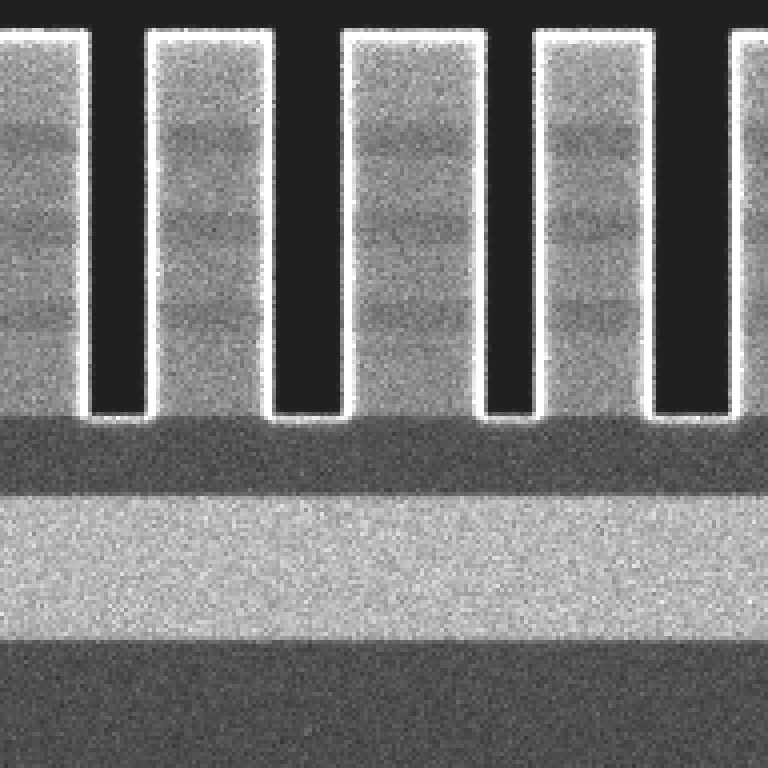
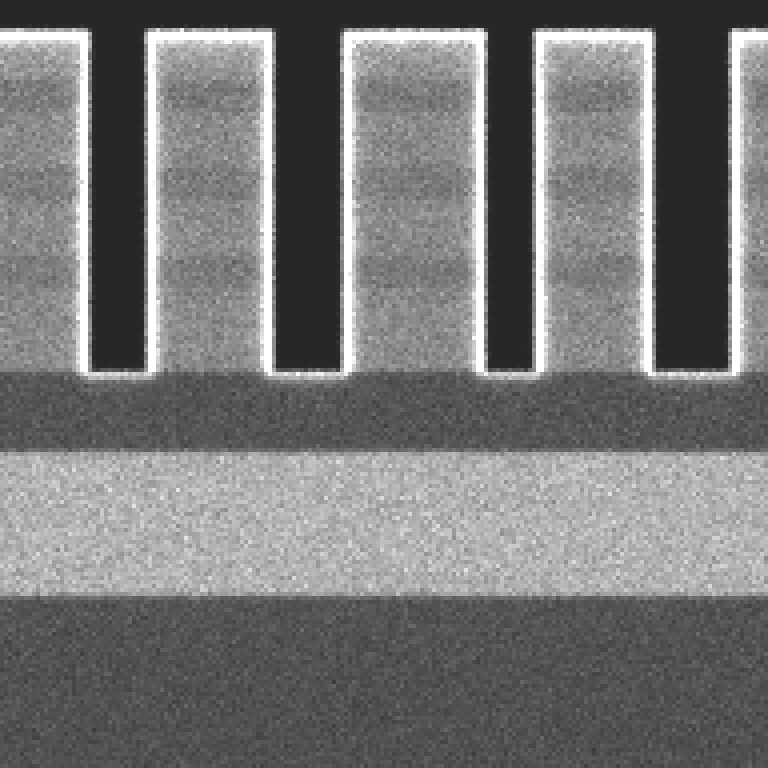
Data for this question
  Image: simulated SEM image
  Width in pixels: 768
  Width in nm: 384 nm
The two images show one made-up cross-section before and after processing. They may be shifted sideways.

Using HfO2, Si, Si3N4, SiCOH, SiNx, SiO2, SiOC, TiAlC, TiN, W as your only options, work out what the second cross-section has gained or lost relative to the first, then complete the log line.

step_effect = removed TiN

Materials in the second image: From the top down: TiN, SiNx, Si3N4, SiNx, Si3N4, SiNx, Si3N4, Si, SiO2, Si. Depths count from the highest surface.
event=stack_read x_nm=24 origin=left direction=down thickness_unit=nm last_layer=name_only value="TiN 24, SiNx 16, Si3N4 28, SiNx 16, Si3N4 28, SiNx 16, Si3N4 42, Si 40, SiO2 72, Si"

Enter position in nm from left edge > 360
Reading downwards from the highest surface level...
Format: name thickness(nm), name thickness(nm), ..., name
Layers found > empty 170, Si 40, SiO2 72, Si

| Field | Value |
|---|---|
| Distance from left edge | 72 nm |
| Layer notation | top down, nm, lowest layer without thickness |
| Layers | empty 170, Si 40, SiO2 72, Si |